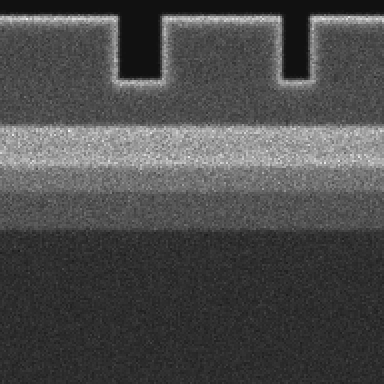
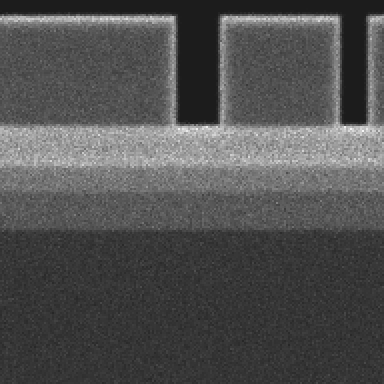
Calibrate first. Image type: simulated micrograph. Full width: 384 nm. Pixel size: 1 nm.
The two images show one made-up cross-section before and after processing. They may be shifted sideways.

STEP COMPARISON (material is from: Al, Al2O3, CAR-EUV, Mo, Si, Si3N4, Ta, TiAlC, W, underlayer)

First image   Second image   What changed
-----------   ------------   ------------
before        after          underlayer, removed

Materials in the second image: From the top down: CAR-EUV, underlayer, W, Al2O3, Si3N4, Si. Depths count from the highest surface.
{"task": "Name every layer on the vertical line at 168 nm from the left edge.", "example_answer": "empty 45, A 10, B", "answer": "CAR-EUV 64, underlayer 46, W 40, Al2O3 26, Si3N4 38, Si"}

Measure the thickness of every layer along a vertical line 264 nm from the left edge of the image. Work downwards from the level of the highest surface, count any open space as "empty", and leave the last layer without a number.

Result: CAR-EUV 64, underlayer 46, W 40, Al2O3 26, Si3N4 38, Si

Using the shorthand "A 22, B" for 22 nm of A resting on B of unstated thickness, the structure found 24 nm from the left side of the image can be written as CAR-EUV 64, underlayer 46, W 40, Al2O3 26, Si3N4 38, Si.